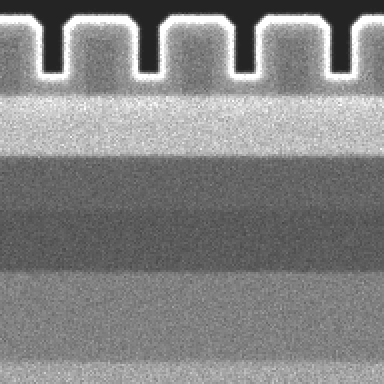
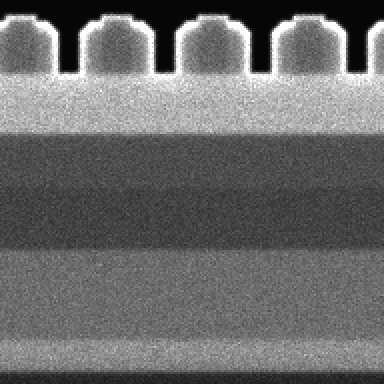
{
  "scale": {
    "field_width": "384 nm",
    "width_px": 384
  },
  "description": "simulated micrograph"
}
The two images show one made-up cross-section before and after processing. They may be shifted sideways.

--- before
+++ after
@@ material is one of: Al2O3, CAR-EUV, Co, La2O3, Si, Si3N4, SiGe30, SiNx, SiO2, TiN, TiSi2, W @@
Al2O3 removed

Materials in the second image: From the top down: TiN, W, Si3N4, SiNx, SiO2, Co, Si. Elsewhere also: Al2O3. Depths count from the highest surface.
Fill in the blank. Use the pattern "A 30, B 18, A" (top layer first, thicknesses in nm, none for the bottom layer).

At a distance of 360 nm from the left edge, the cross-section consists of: empty 58, W 60, Si3N4 54, SiNx 62, SiO2 90, Co 32, Si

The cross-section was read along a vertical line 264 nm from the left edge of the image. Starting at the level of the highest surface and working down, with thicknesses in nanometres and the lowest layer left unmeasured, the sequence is empty 58, W 60, Si3N4 54, SiNx 62, SiO2 90, Co 32, Si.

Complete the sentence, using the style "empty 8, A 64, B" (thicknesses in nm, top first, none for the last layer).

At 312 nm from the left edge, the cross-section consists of TiN 58, W 60, Si3N4 54, SiNx 62, SiO2 90, Co 32, Si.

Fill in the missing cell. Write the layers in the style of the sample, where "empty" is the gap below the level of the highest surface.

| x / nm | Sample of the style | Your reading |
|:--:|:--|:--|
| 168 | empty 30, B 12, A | empty 58, W 60, Si3N4 54, SiNx 62, SiO2 90, Co 32, Si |